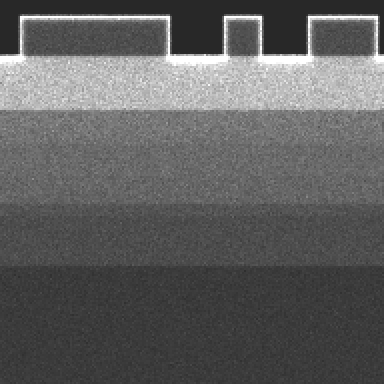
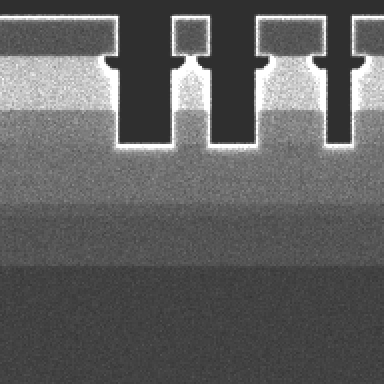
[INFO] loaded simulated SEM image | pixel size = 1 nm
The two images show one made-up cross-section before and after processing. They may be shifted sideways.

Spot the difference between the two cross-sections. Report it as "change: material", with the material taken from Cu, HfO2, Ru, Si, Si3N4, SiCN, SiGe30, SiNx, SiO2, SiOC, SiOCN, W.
removed: HfO2 and Ru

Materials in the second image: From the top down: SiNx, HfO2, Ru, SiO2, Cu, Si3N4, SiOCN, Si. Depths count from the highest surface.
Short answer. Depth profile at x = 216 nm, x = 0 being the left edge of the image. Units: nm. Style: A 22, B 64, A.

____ empty 128, SiO2 32, Cu 28, Si3N4 12, SiOCN 50, Si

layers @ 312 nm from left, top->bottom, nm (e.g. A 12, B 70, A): SiNx 40, empty 8, HfO2 46, Ru 34, SiO2 32, Cu 28, Si3N4 12, SiOCN 50, Si